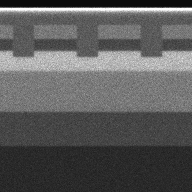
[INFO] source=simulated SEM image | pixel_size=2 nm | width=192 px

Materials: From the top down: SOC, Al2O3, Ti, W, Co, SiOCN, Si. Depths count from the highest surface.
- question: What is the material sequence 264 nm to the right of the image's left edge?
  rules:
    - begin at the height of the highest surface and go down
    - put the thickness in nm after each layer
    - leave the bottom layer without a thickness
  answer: SOC 34, Al2O3 28, Ti 24, W 40, Co 82, SiOCN 68, Si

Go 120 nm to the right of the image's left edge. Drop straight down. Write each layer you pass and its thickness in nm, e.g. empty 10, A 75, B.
SOC 34, Al2O3 28, Ti 24, W 40, Co 82, SiOCN 68, Si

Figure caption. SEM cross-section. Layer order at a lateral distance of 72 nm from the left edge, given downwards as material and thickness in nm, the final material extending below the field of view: SOC 34, Al2O3 28, Ti 24, W 40, Co 82, SiOCN 68, Si